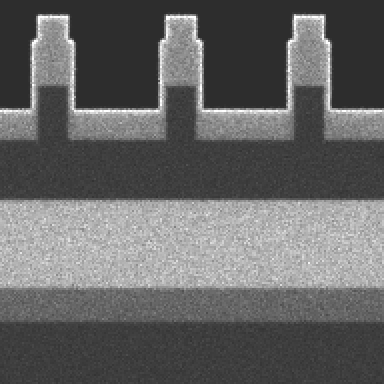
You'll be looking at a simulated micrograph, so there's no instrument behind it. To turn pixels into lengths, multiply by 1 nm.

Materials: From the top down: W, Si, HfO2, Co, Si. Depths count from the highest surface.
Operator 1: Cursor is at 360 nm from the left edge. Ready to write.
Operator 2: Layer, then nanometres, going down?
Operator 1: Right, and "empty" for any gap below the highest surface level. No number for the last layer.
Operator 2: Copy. empty 94, W 30, Si 60, HfO2 88, Co 34, Si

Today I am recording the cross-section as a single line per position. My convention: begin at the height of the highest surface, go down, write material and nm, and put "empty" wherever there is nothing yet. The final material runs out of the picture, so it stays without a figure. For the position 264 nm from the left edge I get empty 94, W 30, Si 60, HfO2 88, Co 34, Si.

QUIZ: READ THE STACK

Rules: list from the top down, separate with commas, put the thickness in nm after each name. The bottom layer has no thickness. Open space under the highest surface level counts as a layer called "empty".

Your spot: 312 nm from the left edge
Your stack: W 70, Si 114, HfO2 88, Co 34, Si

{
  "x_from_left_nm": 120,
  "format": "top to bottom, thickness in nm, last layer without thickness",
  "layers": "empty 94, W 30, Si 60, HfO2 88, Co 34, Si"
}